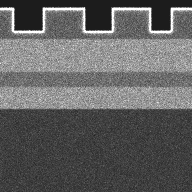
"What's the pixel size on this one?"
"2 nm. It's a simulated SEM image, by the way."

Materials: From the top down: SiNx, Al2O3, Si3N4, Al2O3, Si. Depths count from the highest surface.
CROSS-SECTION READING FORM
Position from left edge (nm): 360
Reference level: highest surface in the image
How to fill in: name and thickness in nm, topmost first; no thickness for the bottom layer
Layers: SiNx 62, Al2O3 66, Si3N4 30, Al2O3 44, Si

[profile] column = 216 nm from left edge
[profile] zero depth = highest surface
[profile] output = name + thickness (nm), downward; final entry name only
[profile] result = empty 46, SiNx 16, Al2O3 66, Si3N4 30, Al2O3 44, Si